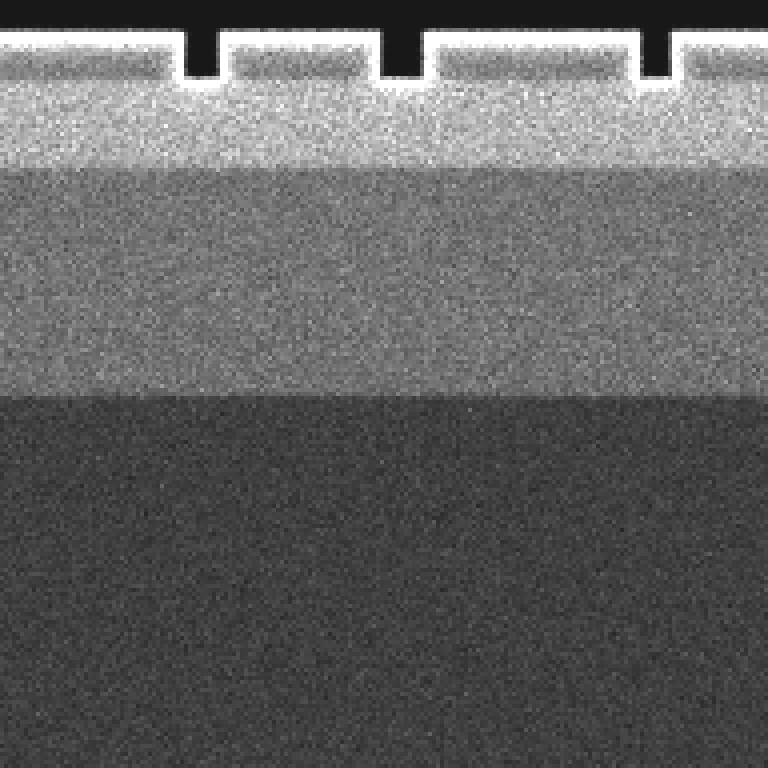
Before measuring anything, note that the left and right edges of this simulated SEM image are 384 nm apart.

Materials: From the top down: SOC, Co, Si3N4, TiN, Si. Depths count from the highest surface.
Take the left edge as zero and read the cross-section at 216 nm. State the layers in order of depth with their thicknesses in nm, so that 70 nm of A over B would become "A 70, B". SOC 24, Co 44, Si3N4 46, TiN 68, Si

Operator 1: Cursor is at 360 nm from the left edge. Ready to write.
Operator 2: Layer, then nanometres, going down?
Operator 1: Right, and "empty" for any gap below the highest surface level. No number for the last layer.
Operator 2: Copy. SOC 24, Co 44, Si3N4 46, TiN 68, Si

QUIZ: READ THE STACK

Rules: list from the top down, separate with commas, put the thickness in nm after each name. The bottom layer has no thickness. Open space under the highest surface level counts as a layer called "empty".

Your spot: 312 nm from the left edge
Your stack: SOC 24, Co 44, Si3N4 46, TiN 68, Si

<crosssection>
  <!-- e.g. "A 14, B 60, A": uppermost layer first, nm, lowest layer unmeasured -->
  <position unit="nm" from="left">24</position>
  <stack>SOC 24, Co 44, Si3N4 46, TiN 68, Si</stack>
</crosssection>